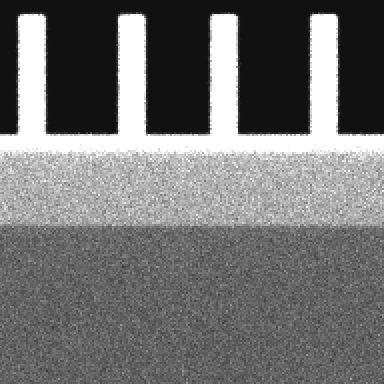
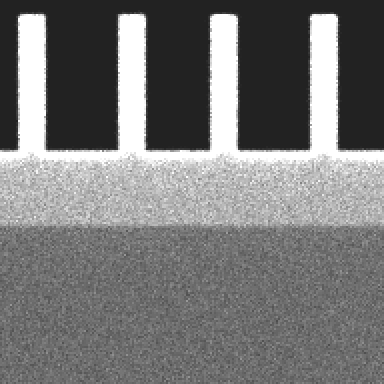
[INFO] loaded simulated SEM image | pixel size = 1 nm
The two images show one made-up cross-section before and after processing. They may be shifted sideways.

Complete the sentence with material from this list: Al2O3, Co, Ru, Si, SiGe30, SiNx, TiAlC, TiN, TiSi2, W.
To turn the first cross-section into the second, TiN must be removed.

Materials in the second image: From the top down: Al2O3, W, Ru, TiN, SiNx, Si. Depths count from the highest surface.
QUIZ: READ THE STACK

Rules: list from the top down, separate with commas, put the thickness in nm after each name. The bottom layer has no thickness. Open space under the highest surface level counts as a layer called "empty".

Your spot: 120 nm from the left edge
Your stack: Al2O3 42, W 68, Ru 10, TiN 16, SiNx 74, Si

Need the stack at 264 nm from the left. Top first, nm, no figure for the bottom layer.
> empty 136, SiNx 74, Si